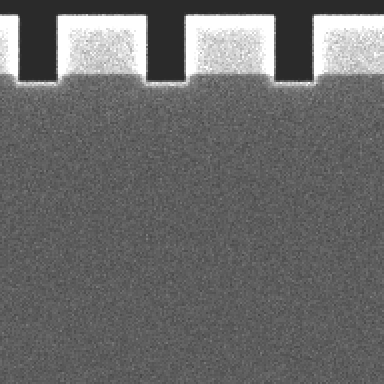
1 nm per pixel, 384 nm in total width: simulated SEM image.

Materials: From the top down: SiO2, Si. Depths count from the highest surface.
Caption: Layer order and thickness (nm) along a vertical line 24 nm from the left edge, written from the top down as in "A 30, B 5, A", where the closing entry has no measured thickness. empty 66, Si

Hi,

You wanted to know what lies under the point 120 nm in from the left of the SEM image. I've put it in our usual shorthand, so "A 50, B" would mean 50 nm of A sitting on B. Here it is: SiO2 58, Si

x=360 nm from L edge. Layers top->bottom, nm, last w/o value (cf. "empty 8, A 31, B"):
SiO2 58, Si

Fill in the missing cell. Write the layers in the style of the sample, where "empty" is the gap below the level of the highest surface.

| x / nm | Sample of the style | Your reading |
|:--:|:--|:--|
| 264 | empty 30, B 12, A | SiO2 58, Si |